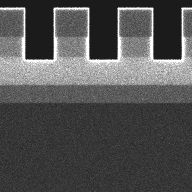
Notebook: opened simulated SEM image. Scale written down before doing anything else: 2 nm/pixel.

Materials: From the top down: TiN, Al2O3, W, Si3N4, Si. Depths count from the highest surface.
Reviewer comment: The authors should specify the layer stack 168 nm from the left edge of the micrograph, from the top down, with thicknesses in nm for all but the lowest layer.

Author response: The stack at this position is TiN 58, Al2O3 40, W 56, Si3N4 36, Si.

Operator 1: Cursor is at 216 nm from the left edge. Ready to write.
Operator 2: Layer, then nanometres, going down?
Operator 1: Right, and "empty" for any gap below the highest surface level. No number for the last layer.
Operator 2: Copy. empty 104, W 50, Si3N4 36, Si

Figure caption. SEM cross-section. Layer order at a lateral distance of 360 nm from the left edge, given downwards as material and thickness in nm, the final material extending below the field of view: empty 104, W 50, Si3N4 36, Si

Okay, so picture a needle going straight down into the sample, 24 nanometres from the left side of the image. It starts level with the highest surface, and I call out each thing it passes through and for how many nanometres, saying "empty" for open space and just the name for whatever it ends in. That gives TiN 58, Al2O3 40, W 56, Si3N4 36, Si